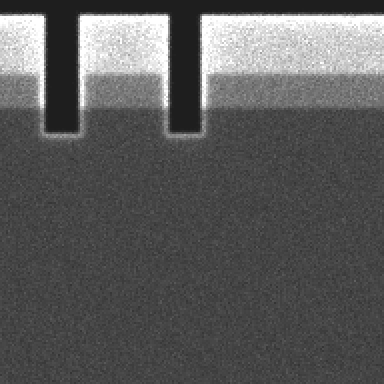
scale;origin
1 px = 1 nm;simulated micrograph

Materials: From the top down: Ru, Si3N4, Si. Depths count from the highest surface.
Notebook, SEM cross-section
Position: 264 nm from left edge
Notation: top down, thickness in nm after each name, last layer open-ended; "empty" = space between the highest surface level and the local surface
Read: Ru 58, Si3N4 34, Si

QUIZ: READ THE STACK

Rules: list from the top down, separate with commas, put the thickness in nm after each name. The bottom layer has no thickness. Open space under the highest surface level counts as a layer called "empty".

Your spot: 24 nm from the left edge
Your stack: Ru 58, Si3N4 34, Si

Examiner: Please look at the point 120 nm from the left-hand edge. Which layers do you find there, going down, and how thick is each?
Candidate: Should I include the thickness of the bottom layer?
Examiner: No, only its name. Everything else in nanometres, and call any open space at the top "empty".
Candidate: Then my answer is Ru 58, Si3N4 34, Si